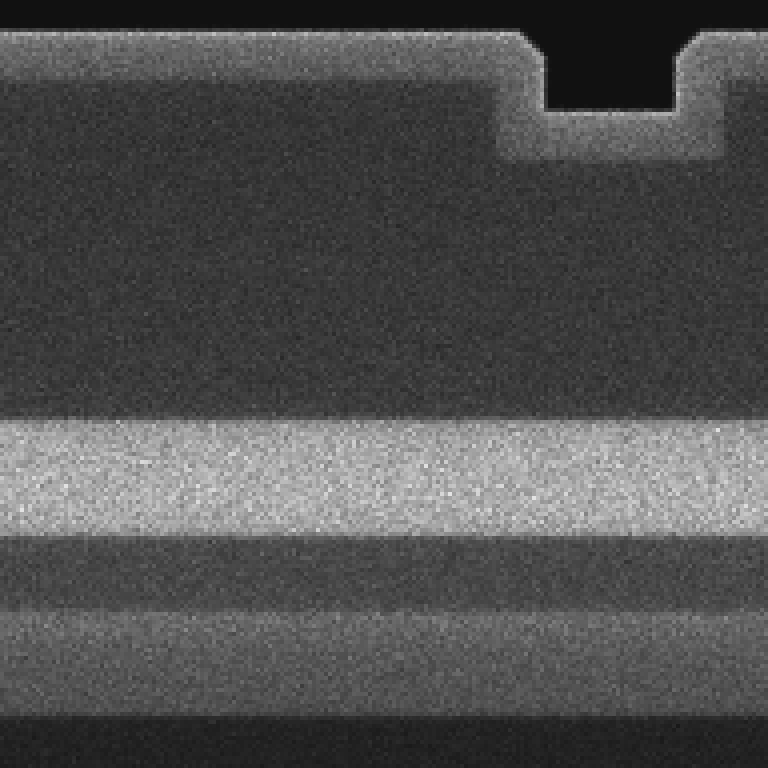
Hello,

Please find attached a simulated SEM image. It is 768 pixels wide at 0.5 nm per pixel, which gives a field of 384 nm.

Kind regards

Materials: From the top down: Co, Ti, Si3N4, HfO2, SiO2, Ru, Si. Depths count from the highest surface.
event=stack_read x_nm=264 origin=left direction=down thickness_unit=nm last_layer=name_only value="empty 6, Co 58, Ti 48, Si3N4 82, HfO2 58, SiO2 38, Ru 52, Si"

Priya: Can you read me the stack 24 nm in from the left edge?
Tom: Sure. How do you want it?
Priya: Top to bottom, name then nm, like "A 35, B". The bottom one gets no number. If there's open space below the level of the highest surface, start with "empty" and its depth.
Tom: Co 24, Ti 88, Si3N4 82, HfO2 58, SiO2 38, Ru 52, Si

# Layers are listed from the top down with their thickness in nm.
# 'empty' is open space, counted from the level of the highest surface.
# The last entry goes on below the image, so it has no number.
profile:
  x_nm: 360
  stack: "Co 64, Ti 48, Si3N4 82, HfO2 58, SiO2 38, Ru 52, Si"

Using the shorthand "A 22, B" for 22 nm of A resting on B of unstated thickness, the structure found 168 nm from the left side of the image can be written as Co 24, Ti 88, Si3N4 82, HfO2 58, SiO2 38, Ru 52, Si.